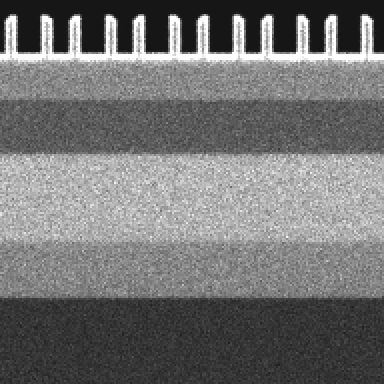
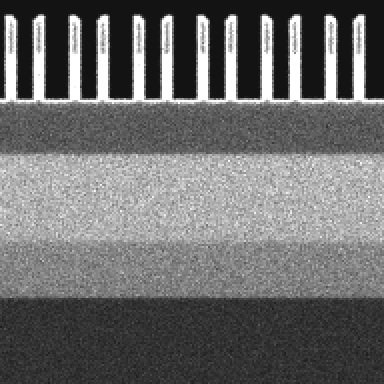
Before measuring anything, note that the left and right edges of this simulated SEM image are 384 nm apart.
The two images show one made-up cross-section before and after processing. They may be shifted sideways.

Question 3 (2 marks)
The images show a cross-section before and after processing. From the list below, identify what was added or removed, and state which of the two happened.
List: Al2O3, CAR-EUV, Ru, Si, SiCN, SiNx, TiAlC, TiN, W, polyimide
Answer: Al2O3 was removed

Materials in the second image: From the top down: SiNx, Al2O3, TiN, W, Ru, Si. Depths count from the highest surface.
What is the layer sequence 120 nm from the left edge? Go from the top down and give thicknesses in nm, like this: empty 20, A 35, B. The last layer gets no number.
empty 84, TiN 54, W 88, Ru 56, Si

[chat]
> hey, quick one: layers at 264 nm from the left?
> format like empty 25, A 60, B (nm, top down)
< SiNx 38, Al2O3 46, TiN 54, W 88, Ru 56, Si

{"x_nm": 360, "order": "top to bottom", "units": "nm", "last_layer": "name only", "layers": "SiNx 38, Al2O3 46, TiN 54, W 88, Ru 56, Si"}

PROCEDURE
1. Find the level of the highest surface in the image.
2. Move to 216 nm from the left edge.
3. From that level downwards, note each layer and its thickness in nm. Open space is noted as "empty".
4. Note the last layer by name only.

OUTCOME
empty 84, TiN 54, W 88, Ru 56, Si